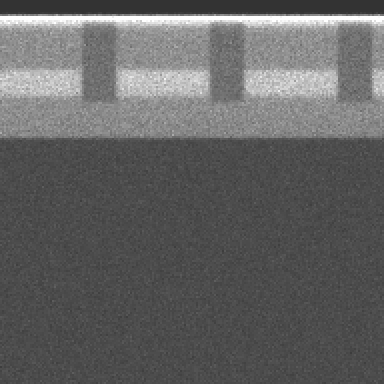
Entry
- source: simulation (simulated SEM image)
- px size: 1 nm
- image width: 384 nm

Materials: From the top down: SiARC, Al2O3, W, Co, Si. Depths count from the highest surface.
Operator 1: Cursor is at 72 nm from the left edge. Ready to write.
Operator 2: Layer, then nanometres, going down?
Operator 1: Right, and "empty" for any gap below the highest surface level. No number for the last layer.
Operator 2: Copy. SiARC 6, Al2O3 48, W 26, Co 42, Si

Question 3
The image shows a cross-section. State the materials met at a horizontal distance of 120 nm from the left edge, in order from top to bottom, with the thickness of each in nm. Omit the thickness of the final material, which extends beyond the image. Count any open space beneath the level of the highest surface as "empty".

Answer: SiARC 6, Al2O3 48, W 26, Co 42, Si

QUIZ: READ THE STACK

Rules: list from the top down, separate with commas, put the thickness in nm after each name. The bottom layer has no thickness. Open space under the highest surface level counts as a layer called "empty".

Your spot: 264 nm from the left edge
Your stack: SiARC 6, Al2O3 48, W 26, Co 42, Si